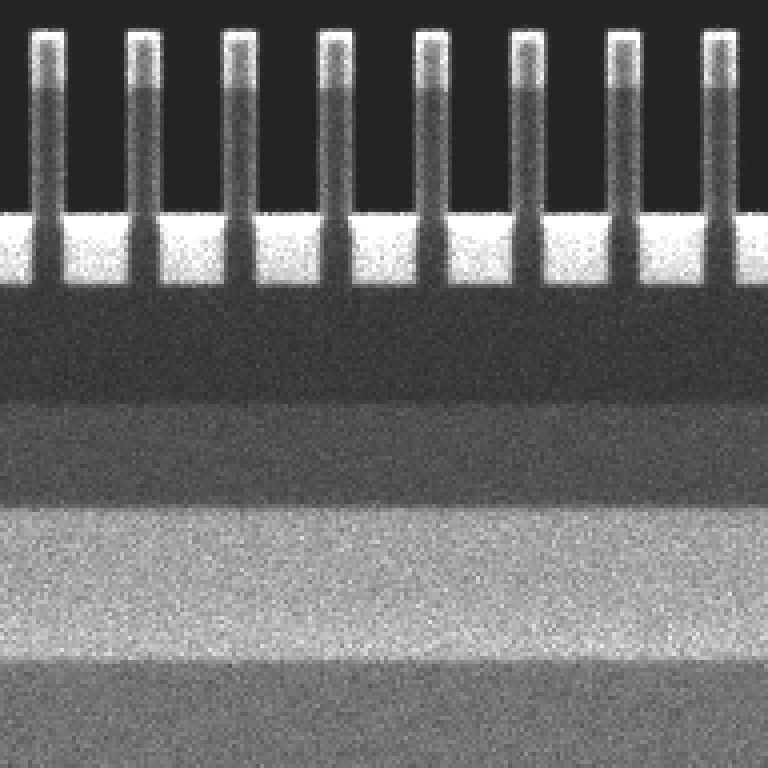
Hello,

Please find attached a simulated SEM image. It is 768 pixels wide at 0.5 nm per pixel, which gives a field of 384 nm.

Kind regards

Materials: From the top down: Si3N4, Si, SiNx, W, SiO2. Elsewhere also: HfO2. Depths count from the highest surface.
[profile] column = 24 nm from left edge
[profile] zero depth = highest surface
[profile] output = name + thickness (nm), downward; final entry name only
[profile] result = Si3N4 28, Si 158, SiNx 52, W 76, SiO2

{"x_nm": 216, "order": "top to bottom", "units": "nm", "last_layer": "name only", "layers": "Si3N4 28, Si 158, SiNx 52, W 76, SiO2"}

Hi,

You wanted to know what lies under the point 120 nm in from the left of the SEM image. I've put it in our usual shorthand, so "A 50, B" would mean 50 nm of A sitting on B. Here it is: Si3N4 28, Si 158, SiNx 52, W 76, SiO2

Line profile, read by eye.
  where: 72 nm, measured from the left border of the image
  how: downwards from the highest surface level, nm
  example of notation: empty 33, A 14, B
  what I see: Si3N4 28, Si 158, SiNx 52, W 76, SiO2